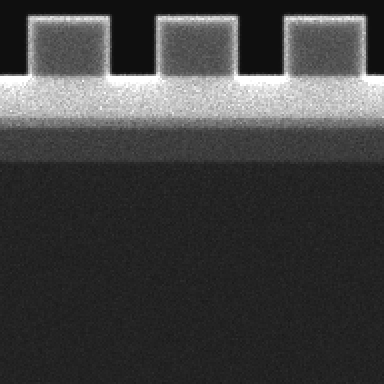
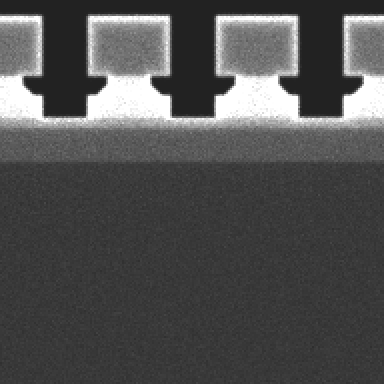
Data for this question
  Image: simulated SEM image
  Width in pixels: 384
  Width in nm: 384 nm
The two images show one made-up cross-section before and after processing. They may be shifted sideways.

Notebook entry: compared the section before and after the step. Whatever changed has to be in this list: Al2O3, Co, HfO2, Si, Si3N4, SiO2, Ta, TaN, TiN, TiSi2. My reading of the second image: HfO2 removed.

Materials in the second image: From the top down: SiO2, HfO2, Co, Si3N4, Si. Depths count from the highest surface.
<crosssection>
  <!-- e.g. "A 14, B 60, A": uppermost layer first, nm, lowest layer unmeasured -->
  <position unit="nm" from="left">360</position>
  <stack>SiO2 60, empty 12, HfO2 30, Co 10, Si3N4 34, Si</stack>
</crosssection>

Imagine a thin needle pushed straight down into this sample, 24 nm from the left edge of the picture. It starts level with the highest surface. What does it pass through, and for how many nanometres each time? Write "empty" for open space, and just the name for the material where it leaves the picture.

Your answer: SiO2 60, empty 12, HfO2 30, Co 10, Si3N4 34, Si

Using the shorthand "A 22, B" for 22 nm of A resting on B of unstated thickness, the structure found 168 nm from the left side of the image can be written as SiO2 60, empty 20, HfO2 22, Co 10, Si3N4 34, Si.